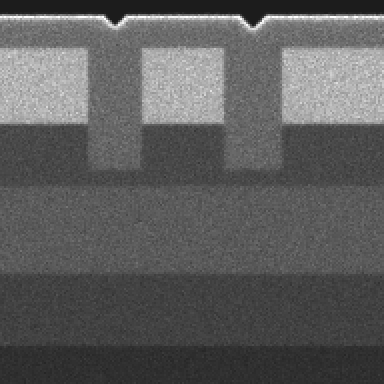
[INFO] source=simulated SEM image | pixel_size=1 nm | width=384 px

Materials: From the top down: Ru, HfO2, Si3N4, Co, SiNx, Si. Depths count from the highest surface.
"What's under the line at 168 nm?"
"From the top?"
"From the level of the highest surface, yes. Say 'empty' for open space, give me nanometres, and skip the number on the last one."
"Ru 32, HfO2 76, Si3N4 62, Co 88, SiNx 72, Si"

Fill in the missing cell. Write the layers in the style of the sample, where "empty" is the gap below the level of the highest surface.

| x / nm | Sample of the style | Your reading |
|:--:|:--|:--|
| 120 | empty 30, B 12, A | empty 6, Ru 148, Si3N4 16, Co 88, SiNx 72, Si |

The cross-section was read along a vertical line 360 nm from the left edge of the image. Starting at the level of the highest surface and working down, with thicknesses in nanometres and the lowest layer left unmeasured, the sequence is Ru 32, HfO2 76, Si3N4 62, Co 88, SiNx 72, Si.